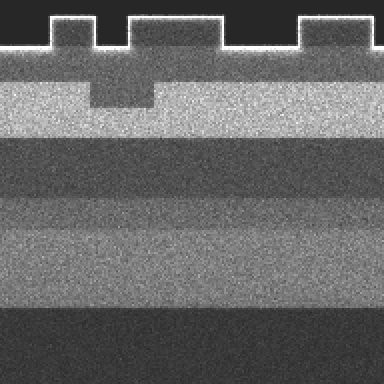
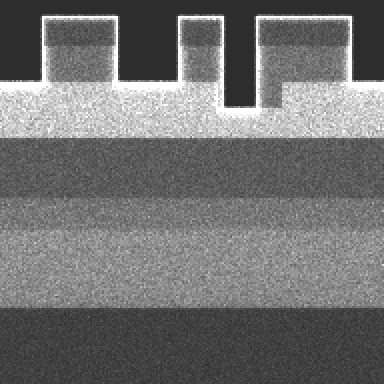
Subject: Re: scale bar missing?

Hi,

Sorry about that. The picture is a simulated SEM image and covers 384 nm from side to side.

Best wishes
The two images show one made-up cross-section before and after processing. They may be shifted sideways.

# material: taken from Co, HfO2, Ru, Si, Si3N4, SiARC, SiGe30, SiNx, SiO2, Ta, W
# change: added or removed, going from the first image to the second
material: SiO2
change: removed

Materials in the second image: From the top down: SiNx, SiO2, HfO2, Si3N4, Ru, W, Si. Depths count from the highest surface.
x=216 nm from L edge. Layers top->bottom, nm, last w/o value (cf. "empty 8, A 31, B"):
SiNx 30, SiO2 36, HfO2 56, Si3N4 60, Ru 32, W 78, Si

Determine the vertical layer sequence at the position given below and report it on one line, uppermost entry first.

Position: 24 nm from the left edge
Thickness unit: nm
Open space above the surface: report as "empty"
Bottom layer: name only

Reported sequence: empty 66, HfO2 56, Si3N4 60, Ru 32, W 78, Si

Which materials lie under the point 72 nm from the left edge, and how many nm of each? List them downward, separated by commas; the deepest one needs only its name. SiNx 30, SiO2 36, HfO2 56, Si3N4 60, Ru 32, W 78, Si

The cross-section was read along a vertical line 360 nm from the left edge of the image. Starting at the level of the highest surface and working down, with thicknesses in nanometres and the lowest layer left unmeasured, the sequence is empty 66, HfO2 56, Si3N4 60, Ru 32, W 78, Si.